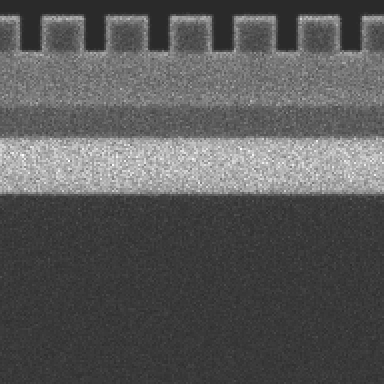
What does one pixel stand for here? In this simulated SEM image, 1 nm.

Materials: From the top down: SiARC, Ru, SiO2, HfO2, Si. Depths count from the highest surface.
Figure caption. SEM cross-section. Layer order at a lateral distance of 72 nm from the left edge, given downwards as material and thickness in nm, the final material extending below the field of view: SiARC 36, Ru 54, SiO2 32, HfO2 56, Si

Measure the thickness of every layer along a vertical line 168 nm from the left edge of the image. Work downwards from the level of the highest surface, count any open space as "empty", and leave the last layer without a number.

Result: empty 36, Ru 54, SiO2 32, HfO2 56, Si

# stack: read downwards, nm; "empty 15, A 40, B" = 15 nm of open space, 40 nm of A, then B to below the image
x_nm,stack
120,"SiARC 36, Ru 54, SiO2 32, HfO2 56, Si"